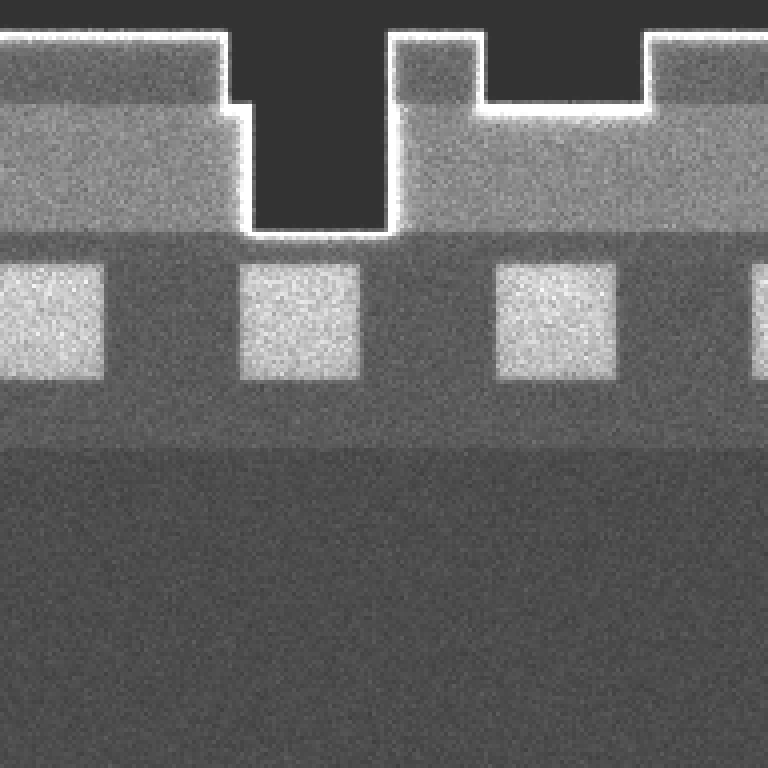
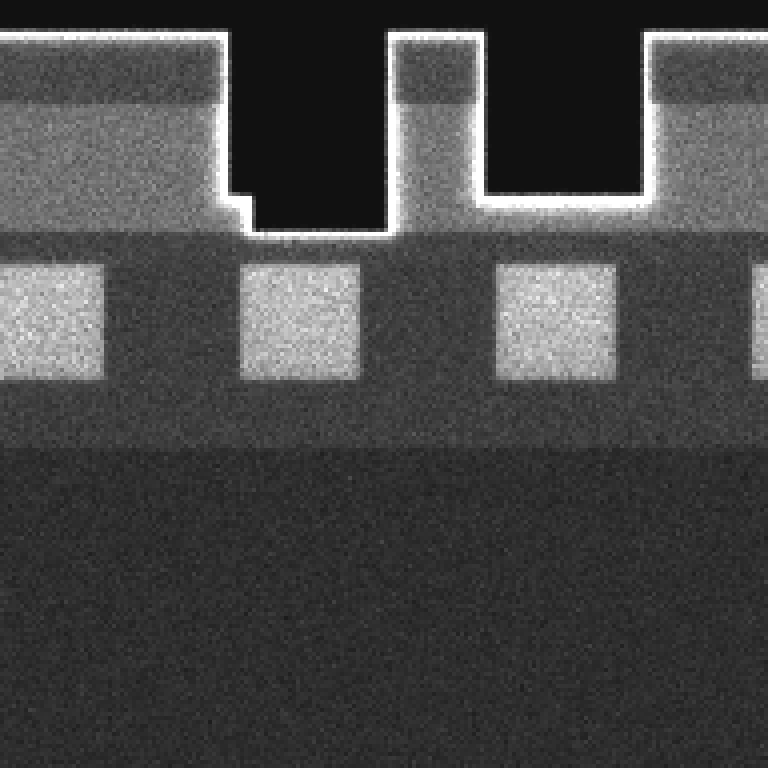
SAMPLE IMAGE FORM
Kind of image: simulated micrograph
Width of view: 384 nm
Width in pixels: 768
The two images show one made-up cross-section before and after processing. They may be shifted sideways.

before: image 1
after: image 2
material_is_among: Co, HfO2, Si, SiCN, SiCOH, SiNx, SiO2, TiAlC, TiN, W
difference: SiO2, removed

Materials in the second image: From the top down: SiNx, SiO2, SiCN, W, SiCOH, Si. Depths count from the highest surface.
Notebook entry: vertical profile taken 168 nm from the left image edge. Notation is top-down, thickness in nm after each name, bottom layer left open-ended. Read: empty 100, SiCN 16, W 58, SiCOH 34, Si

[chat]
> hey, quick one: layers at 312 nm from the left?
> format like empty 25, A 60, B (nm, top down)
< empty 82, SiO2 18, SiCN 16, SiCOH 92, Si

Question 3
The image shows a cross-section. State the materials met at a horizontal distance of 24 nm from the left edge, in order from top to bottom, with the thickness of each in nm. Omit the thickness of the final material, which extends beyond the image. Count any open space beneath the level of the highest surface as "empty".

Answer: SiNx 36, SiO2 64, SiCN 16, W 58, SiCOH 34, Si